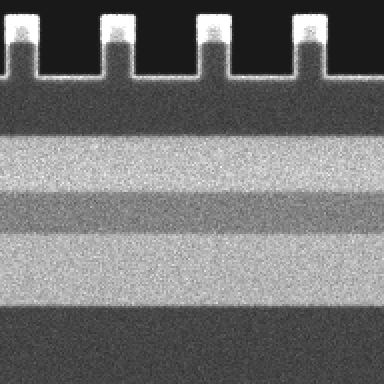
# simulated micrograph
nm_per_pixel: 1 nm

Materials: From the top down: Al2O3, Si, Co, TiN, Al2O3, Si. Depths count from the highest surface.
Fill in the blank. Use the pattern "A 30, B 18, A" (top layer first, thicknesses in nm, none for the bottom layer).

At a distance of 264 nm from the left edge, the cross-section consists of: empty 60, Si 60, Co 56, TiN 42, Al2O3 72, Si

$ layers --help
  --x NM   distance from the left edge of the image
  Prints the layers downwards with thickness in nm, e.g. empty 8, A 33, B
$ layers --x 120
Al2O3 26, Si 94, Co 56, TiN 42, Al2O3 72, Si